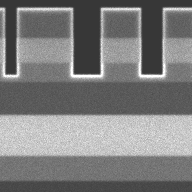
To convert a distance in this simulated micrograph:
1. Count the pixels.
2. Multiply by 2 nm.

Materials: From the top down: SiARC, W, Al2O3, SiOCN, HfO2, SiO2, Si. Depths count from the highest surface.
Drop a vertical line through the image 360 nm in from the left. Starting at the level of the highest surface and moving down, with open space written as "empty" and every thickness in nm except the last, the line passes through SiARC 60, W 50, Al2O3 38, SiOCN 66, HfO2 82, SiO2 50, Si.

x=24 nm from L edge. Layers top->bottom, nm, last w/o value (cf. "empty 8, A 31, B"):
empty 134, Al2O3 14, SiOCN 66, HfO2 82, SiO2 50, Si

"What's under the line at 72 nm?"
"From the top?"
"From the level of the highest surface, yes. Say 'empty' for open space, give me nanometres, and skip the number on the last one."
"SiARC 60, W 50, Al2O3 38, SiOCN 66, HfO2 82, SiO2 50, Si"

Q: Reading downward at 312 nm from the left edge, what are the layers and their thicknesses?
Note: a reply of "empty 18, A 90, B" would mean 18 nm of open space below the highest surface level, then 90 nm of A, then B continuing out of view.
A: empty 134, Al2O3 14, SiOCN 66, HfO2 82, SiO2 50, Si